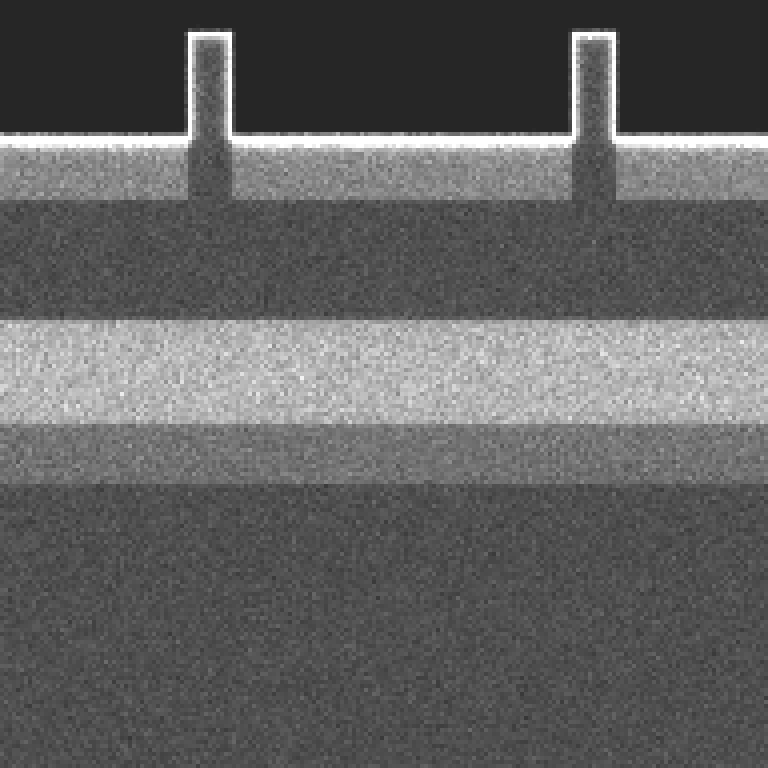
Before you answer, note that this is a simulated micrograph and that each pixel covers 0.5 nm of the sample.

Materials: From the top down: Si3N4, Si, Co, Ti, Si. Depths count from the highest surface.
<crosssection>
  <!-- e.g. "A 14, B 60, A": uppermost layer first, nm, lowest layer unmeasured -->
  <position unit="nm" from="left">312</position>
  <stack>empty 52, Si3N4 32, Si 60, Co 52, Ti 30, Si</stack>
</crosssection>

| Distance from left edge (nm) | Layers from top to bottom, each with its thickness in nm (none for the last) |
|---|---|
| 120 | empty 52, Si3N4 32, Si 60, Co 52, Ti 30, Si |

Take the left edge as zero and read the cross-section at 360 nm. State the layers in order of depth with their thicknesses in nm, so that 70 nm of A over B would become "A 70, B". empty 52, Si3N4 32, Si 60, Co 52, Ti 30, Si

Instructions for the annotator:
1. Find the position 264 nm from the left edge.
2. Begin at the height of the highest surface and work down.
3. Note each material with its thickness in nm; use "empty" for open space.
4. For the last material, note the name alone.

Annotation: empty 52, Si3N4 32, Si 60, Co 52, Ti 30, Si